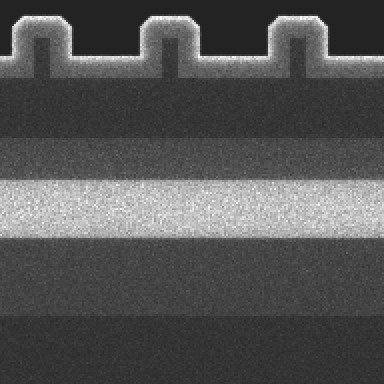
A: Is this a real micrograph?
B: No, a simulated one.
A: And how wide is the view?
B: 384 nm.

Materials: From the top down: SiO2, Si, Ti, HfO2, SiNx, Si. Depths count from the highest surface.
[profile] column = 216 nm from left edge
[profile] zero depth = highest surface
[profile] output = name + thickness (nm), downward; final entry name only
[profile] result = empty 40, SiO2 22, Si 60, Ti 42, HfO2 58, SiNx 78, Si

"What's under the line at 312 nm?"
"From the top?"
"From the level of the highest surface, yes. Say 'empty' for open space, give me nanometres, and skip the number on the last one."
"SiO2 62, Si 60, Ti 42, HfO2 58, SiNx 78, Si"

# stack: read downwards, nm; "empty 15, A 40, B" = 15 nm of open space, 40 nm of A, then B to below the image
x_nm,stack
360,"empty 40, SiO2 22, Si 60, Ti 42, HfO2 58, SiNx 78, Si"